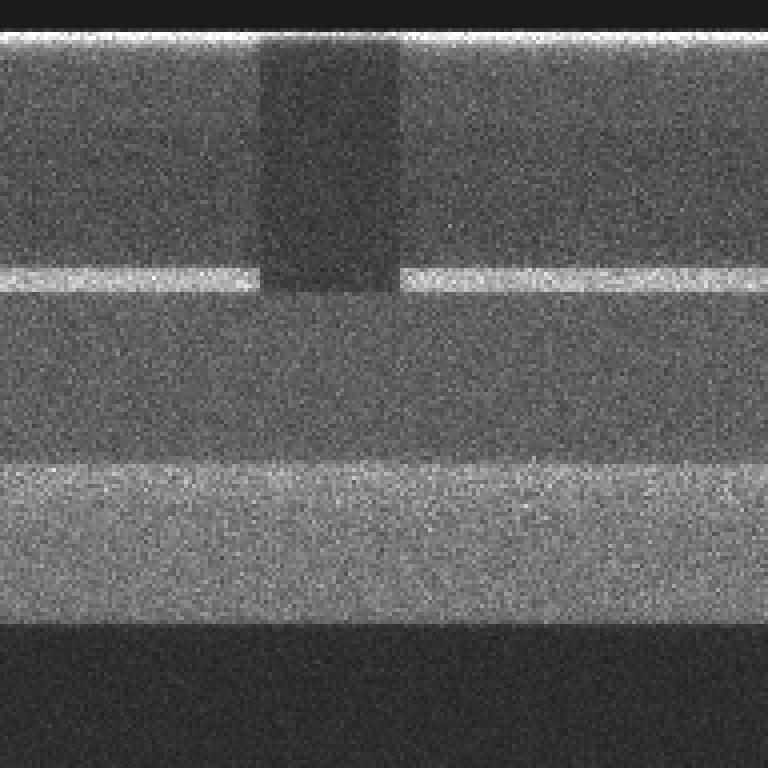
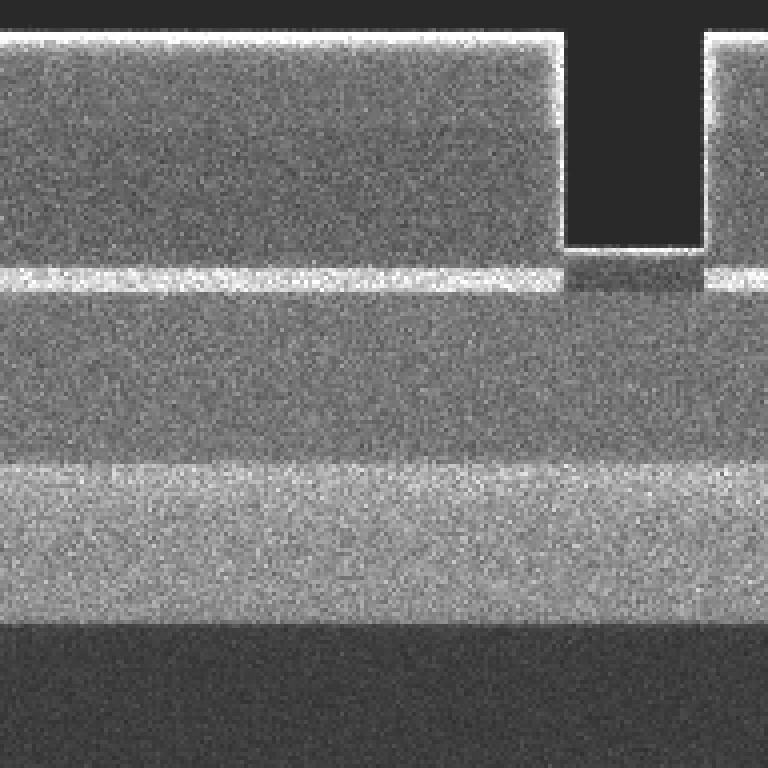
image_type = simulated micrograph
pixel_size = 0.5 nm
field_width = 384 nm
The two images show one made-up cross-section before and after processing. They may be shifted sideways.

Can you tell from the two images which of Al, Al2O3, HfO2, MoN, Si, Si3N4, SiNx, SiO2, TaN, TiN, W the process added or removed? Yes, it removed SiNx.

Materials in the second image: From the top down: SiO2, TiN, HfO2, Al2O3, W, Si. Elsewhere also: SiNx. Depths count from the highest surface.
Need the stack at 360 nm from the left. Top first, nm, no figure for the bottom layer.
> SiO2 48, TiN 70, HfO2 12, Al2O3 86, W 80, Si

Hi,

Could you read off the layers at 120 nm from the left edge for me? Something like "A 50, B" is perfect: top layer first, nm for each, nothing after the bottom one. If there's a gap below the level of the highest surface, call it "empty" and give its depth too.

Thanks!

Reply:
SiO2 48, TiN 70, HfO2 12, Al2O3 86, W 80, Si